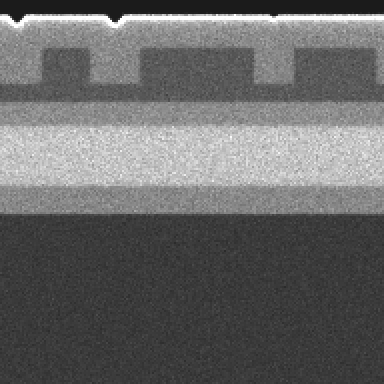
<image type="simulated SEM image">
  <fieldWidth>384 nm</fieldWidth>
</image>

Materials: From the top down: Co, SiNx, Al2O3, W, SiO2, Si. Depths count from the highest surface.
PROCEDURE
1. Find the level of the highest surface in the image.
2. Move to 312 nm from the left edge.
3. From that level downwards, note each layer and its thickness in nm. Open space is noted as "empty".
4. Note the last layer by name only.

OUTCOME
Co 32, SiNx 54, Al2O3 24, W 60, SiO2 28, Si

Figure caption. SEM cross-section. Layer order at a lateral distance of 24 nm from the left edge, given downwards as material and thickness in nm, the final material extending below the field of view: empty 2, Co 66, SiNx 18, Al2O3 24, W 60, SiO2 28, Si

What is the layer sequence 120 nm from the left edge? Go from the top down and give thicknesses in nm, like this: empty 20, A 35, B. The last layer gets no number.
empty 4, Co 64, SiNx 18, Al2O3 24, W 60, SiO2 28, Si